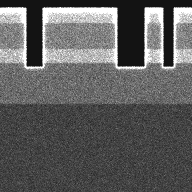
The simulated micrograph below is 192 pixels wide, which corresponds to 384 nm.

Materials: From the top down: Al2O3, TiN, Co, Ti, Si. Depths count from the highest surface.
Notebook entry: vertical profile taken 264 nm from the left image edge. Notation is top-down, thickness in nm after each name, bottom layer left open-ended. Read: empty 118, Ti 74, Si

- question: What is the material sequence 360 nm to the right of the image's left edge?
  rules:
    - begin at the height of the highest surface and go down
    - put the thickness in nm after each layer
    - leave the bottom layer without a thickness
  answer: Al2O3 30, TiN 52, Co 28, Ti 82, Si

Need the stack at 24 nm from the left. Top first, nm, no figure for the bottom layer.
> Al2O3 30, TiN 52, Co 28, Ti 82, Si